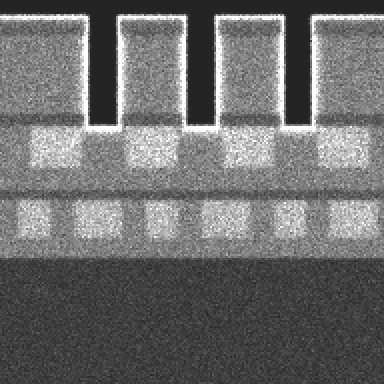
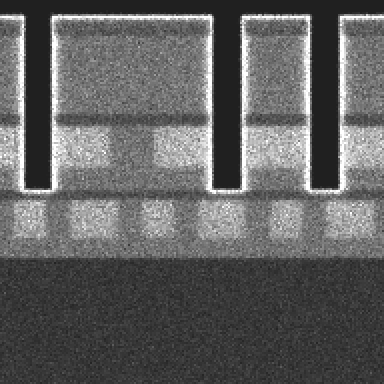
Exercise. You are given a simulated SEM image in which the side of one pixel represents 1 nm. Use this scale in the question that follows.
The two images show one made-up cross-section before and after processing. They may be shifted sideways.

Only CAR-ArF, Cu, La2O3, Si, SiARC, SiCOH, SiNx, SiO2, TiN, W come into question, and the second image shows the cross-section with SiO2 removed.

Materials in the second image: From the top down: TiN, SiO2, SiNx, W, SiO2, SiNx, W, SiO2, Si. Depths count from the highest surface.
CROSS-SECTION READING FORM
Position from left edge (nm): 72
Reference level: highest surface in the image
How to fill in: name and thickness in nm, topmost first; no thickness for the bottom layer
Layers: TiN 20, SiO2 78, SiNx 12, W 42, SiO2 22, SiNx 10, W 38, SiO2 20, Si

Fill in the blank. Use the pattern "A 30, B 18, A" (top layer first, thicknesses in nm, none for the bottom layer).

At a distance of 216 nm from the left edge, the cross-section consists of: empty 174, SiNx 10, W 38, SiO2 20, Si